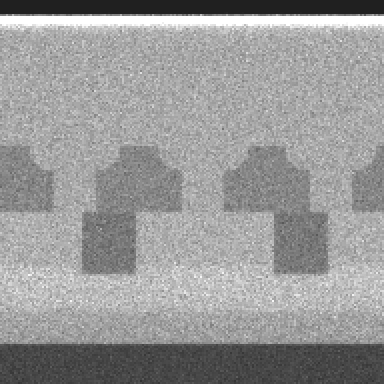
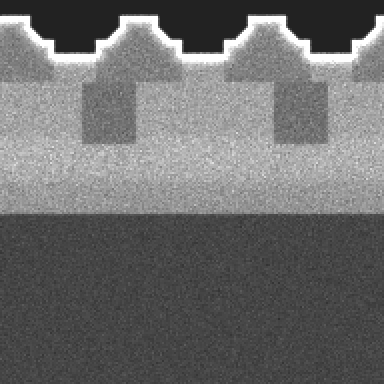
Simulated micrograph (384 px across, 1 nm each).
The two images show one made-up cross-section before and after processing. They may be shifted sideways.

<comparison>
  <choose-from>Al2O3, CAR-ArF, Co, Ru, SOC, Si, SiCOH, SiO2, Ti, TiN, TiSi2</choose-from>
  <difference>SiO2 removed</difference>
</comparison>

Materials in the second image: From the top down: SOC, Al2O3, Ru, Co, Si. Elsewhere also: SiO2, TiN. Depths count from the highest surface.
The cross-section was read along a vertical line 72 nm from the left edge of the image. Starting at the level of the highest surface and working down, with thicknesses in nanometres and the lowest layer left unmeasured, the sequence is empty 38, SiO2 28, Al2O3 54, Ru 46, Co 32, Si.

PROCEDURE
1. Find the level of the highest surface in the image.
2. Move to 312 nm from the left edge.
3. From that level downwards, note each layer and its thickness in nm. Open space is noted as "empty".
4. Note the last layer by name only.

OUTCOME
empty 38, SiO2 28, TiN 62, Ru 38, Co 32, Si